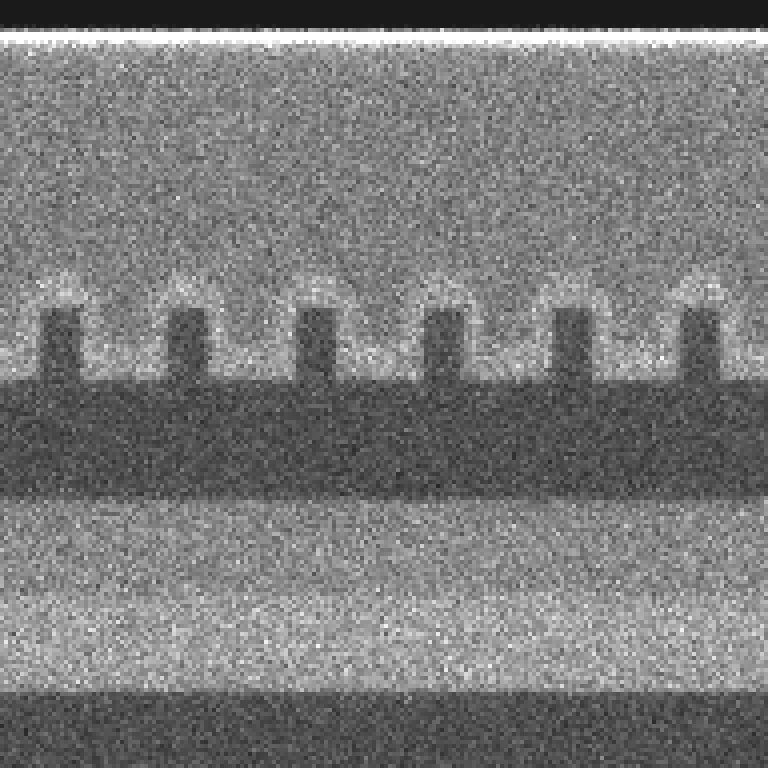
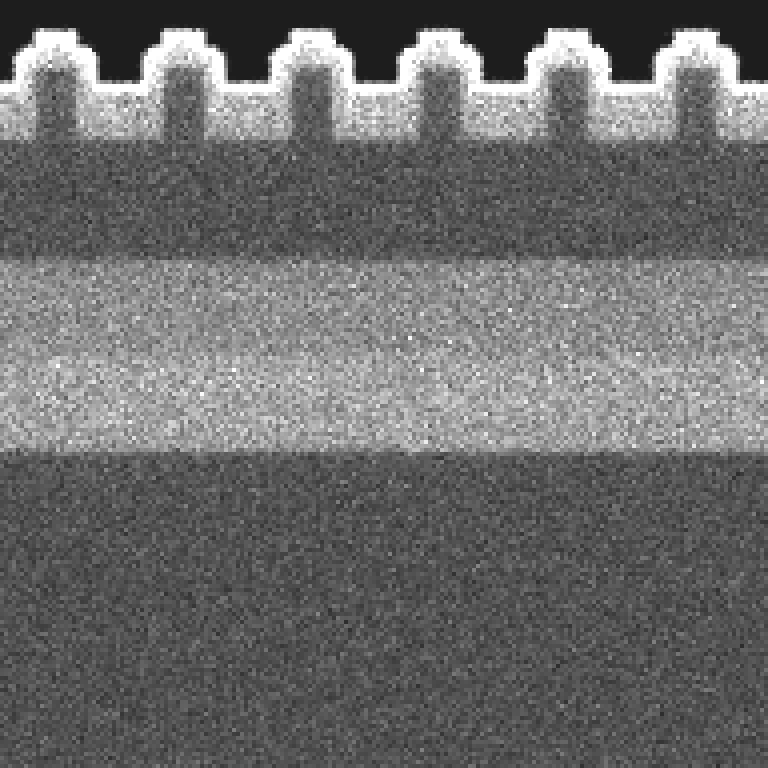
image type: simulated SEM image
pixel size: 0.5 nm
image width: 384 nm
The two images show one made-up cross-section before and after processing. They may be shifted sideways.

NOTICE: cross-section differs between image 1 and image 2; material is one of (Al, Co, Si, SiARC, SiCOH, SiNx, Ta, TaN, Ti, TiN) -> removed: SiNx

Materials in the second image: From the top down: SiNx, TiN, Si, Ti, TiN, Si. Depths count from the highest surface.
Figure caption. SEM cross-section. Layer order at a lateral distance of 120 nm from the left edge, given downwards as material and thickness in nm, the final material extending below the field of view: empty 26, SiNx 10, TiN 18, Si 60, Ti 48, TiN 48, Si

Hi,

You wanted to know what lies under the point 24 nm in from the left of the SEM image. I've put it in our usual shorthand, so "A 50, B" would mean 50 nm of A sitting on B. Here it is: TiN 18, Si 96, Ti 48, TiN 48, Si